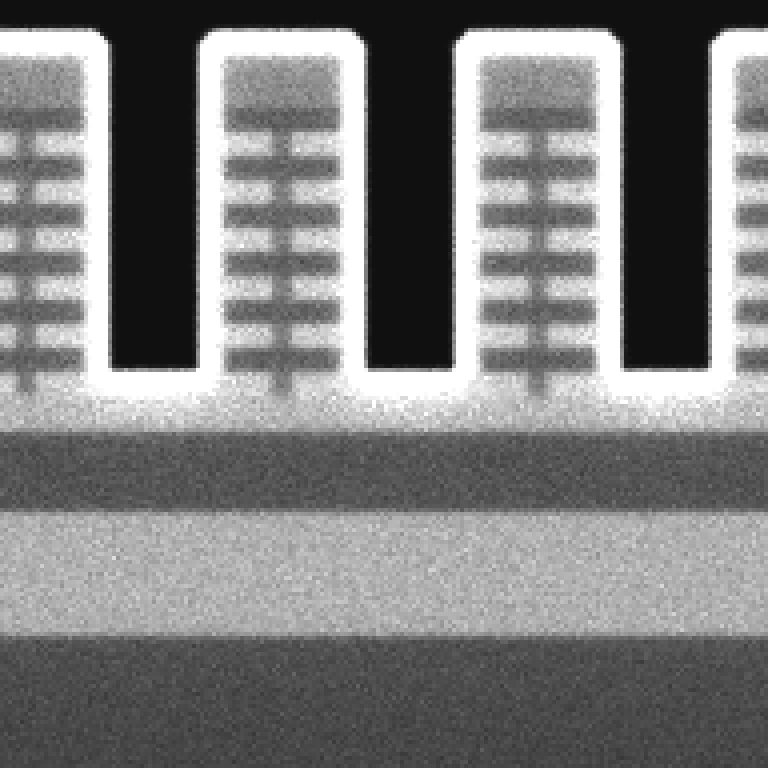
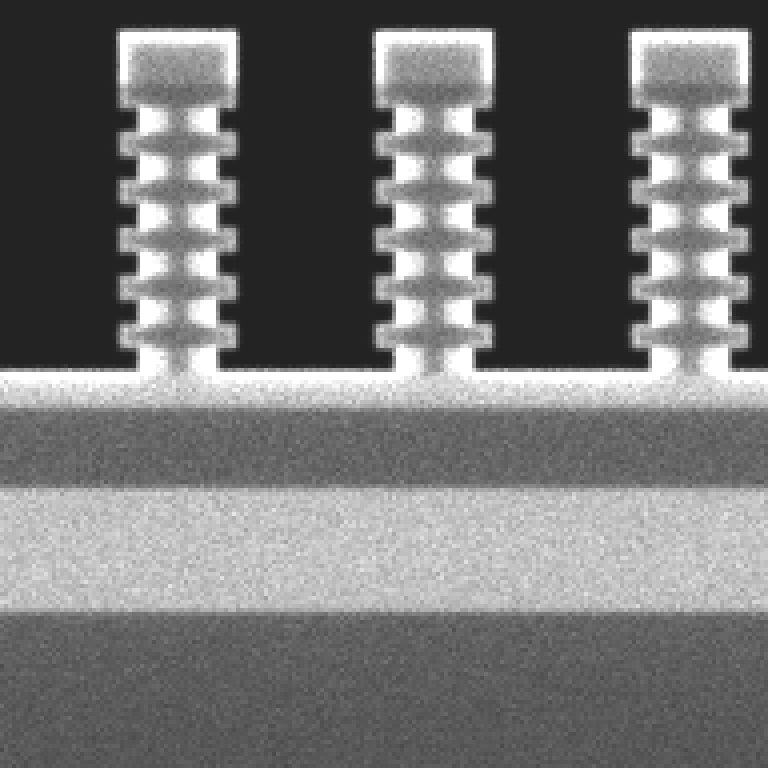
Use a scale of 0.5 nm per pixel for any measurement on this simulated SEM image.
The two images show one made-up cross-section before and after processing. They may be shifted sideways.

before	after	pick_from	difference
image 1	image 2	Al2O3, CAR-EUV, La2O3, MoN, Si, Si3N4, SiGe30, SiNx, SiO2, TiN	Al2O3 removed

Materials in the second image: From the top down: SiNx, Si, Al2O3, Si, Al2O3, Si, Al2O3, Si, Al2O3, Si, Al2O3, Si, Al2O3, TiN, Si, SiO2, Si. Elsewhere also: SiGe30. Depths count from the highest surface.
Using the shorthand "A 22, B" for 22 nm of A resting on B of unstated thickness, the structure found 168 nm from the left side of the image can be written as empty 170, TiN 18, Si 40, SiO2 62, Si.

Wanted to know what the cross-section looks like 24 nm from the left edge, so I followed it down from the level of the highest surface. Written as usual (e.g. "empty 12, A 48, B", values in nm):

empty 170, TiN 18, Si 40, SiO2 62, Si